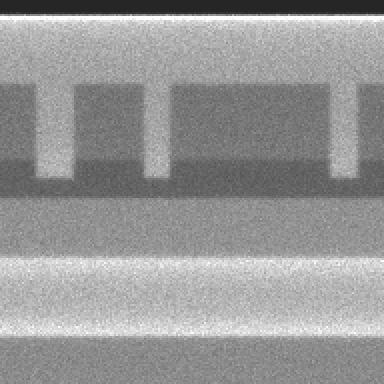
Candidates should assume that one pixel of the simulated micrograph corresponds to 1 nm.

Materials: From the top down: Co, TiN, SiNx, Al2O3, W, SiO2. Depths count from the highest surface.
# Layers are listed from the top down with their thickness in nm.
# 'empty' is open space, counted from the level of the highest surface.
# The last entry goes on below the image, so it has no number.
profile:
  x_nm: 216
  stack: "Co 68, TiN 76, SiNx 38, Al2O3 60, W 78, SiO2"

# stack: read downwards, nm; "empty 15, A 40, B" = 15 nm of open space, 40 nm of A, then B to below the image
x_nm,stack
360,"Co 68, TiN 76, SiNx 38, Al2O3 60, W 78, SiO2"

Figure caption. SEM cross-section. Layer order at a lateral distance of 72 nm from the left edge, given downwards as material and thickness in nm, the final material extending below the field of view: Co 162, SiNx 20, Al2O3 60, W 78, SiO2